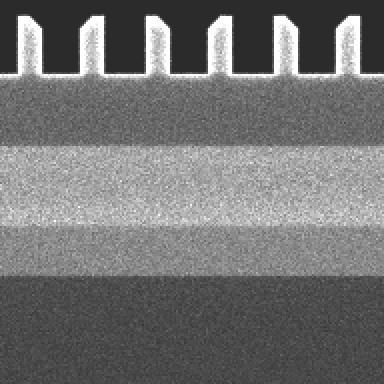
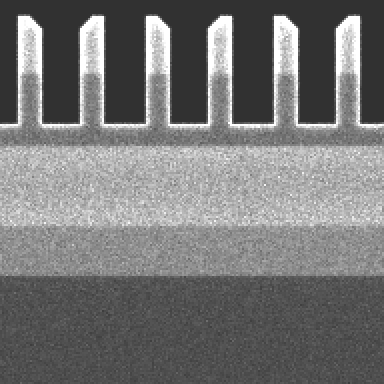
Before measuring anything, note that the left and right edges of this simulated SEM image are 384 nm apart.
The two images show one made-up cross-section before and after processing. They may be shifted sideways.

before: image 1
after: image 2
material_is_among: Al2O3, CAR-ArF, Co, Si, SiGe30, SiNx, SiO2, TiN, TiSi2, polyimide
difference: SiNx, removed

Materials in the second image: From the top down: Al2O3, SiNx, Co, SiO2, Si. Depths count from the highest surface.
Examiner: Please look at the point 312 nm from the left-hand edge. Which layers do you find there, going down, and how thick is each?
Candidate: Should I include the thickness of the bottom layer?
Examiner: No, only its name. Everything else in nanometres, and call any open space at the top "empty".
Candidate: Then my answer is empty 108, SiNx 22, Co 80, SiO2 50, Si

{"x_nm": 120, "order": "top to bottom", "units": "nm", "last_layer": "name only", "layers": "empty 108, SiNx 22, Co 80, SiO2 50, Si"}